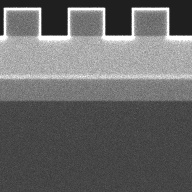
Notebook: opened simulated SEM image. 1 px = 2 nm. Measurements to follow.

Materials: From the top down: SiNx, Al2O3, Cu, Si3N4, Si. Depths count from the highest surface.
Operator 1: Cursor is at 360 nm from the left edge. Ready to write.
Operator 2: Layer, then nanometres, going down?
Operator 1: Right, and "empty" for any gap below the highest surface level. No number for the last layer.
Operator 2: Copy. empty 56, Al2O3 78, Cu 8, Si3N4 44, Si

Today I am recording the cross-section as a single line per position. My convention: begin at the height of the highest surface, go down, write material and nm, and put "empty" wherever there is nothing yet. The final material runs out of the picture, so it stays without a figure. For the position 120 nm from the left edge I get empty 56, Al2O3 78, Cu 8, Si3N4 44, Si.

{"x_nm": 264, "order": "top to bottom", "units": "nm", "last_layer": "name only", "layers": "SiNx 56, Al2O3 78, Cu 8, Si3N4 44, Si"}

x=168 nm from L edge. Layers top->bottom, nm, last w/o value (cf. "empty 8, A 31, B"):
SiNx 56, Al2O3 78, Cu 8, Si3N4 44, Si